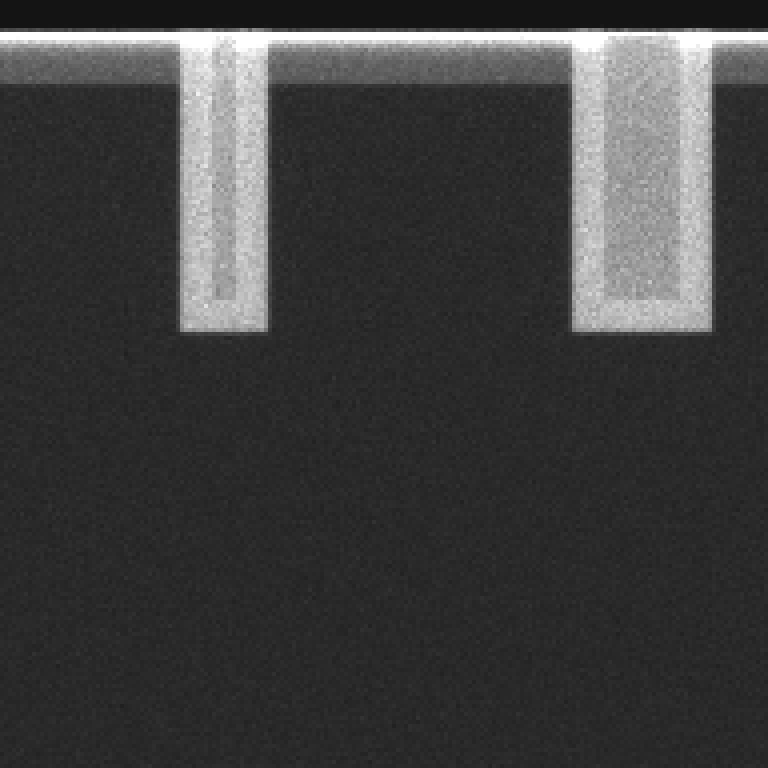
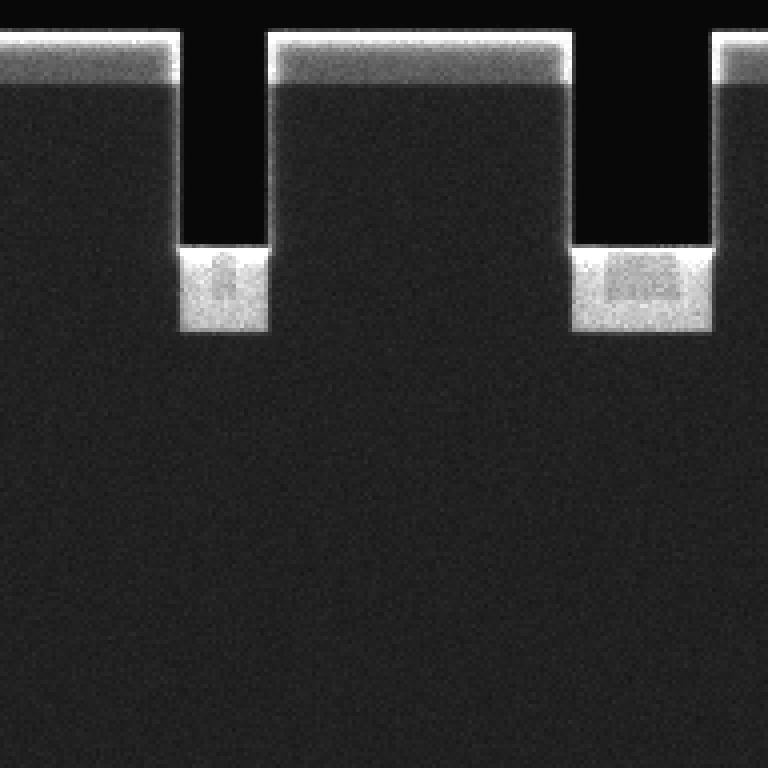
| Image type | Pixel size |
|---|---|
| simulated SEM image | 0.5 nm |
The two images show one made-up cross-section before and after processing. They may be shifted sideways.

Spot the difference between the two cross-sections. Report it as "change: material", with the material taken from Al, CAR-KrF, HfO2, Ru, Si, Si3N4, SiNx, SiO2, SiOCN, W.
removed: HfO2 and W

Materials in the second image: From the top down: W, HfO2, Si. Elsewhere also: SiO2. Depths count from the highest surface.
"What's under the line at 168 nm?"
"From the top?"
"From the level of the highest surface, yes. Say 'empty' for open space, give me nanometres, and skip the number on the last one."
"SiO2 26, Si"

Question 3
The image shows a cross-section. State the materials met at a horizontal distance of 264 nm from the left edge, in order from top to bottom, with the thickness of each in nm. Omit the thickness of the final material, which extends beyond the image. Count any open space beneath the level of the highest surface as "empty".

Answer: SiO2 26, Si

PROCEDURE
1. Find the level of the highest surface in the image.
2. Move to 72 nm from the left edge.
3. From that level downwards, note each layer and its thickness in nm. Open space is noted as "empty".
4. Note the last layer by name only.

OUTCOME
SiO2 26, Si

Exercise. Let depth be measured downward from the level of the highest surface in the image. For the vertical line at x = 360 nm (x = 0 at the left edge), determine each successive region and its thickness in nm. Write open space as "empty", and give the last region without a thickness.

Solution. SiO2 26, Si